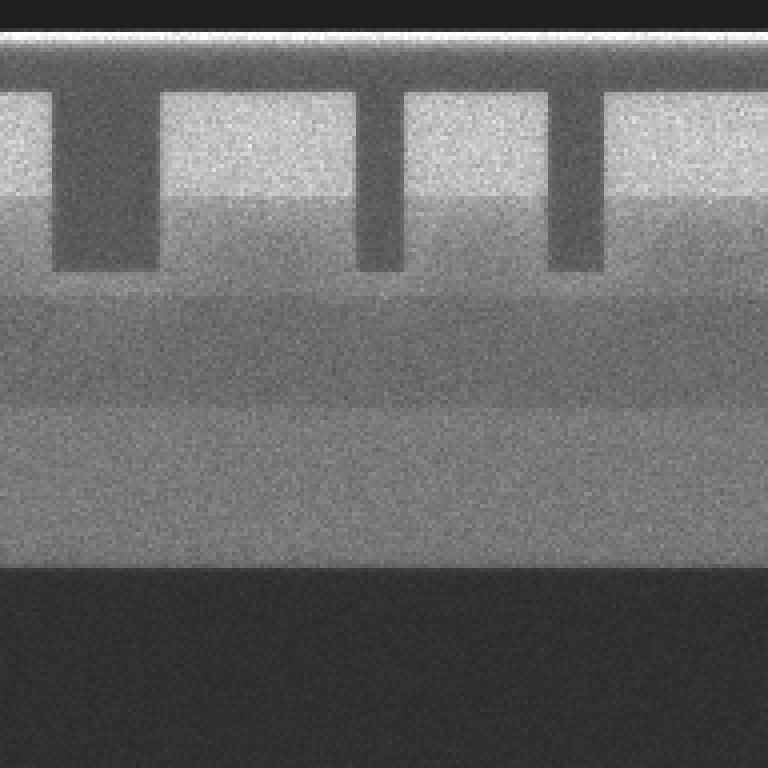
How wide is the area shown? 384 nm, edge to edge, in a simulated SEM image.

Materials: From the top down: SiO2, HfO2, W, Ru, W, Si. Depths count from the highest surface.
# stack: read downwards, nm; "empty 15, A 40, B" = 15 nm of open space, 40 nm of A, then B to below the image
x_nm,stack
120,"SiO2 30, HfO2 52, W 50, Ru 56, W 80, Si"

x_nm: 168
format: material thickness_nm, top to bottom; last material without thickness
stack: SiO2 30, HfO2 52, W 50, Ru 56, W 80, Si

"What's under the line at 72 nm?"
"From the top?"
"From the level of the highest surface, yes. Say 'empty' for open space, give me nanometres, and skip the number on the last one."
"SiO2 120, W 12, Ru 56, W 80, Si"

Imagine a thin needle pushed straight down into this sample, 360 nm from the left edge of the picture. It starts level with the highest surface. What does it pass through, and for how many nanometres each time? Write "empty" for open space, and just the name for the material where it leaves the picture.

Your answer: SiO2 30, HfO2 52, W 50, Ru 56, W 80, Si